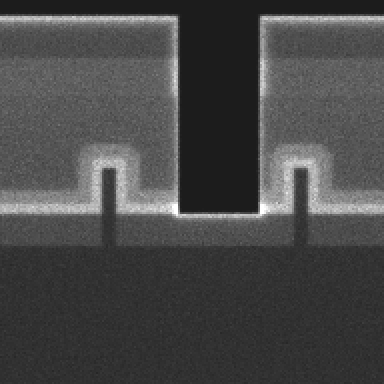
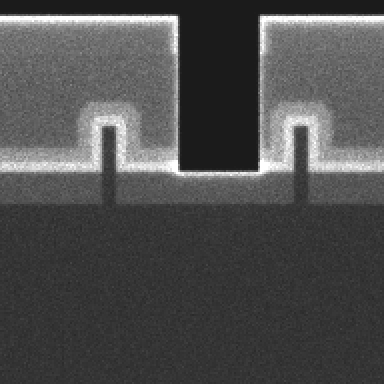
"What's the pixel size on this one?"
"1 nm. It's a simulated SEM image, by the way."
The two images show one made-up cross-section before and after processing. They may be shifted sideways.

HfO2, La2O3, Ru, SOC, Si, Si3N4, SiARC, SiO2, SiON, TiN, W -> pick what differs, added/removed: SOC removed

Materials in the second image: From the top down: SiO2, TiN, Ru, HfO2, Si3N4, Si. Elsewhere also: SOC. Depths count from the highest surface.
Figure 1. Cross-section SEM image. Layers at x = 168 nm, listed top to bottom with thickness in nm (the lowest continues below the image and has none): SiO2 38, TiN 94, Ru 14, HfO2 10, Si3N4 32, Si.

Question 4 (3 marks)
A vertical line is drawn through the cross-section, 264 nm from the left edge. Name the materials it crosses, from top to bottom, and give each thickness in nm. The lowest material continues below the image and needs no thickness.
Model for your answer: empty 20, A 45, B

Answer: SiO2 38, TiN 94, Ru 14, HfO2 10, Si3N4 32, Si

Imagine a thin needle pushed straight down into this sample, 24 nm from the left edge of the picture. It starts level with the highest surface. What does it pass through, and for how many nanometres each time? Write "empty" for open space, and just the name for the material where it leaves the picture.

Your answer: SiO2 38, TiN 94, Ru 14, HfO2 10, Si3N4 32, Si